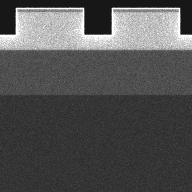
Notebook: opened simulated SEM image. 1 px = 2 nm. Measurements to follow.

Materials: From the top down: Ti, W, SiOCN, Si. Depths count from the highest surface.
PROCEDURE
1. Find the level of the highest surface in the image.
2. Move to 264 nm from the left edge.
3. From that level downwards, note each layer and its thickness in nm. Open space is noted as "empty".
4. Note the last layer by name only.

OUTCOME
Ti 8, W 76, SiOCN 90, Si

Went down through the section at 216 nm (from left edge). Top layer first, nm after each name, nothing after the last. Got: empty 54, W 30, SiOCN 90, Si